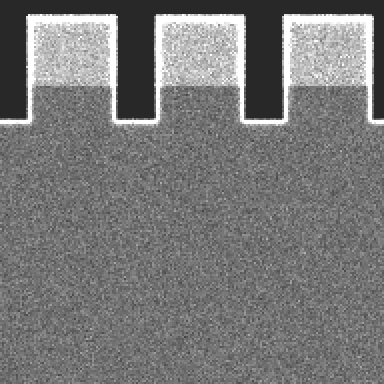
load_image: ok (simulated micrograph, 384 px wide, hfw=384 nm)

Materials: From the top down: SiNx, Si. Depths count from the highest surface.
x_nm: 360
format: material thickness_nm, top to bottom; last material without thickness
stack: SiNx 70, Si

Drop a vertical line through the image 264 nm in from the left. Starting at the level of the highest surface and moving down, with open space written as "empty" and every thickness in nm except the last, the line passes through empty 104, Si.